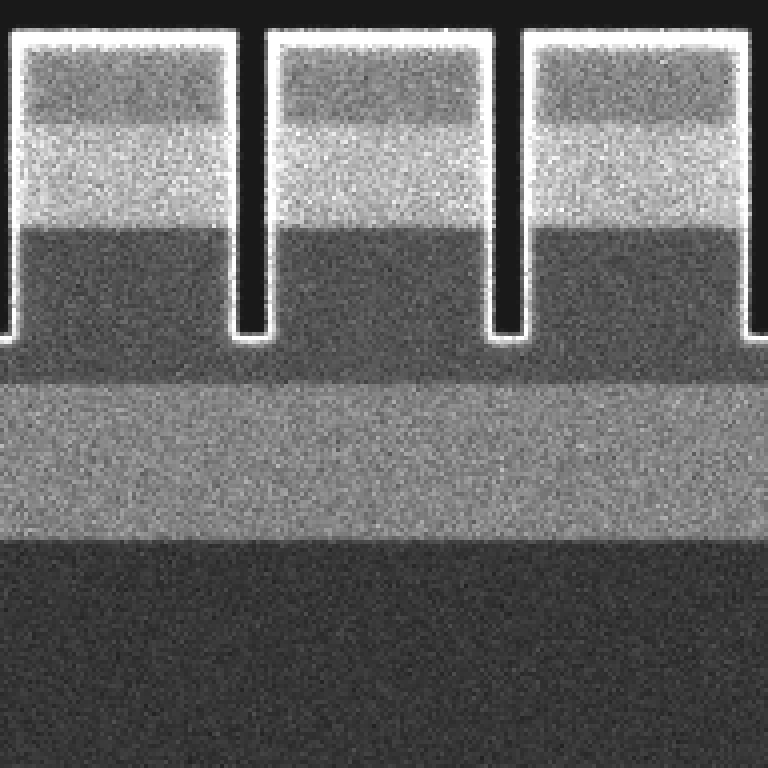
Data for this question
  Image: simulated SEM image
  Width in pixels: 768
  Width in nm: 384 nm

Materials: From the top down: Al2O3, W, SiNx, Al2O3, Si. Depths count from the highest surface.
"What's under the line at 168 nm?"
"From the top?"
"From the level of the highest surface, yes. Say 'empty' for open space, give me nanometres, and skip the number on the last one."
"Al2O3 46, W 52, SiNx 78, Al2O3 78, Si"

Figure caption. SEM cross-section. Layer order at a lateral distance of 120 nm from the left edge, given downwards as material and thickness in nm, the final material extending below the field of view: empty 152, SiNx 24, Al2O3 78, Si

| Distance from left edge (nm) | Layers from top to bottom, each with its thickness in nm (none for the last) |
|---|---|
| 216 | Al2O3 46, W 52, SiNx 78, Al2O3 78, Si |